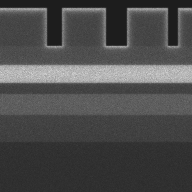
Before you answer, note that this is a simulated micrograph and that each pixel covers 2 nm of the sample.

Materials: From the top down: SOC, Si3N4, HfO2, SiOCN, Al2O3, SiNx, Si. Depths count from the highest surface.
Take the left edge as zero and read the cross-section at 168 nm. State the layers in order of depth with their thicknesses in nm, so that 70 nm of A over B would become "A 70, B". SOC 76, Si3N4 38, HfO2 36, SiOCN 22, Al2O3 42, SiNx 54, Si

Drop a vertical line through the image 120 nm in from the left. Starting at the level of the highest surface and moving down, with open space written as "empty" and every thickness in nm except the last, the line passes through empty 76, Si3N4 38, HfO2 36, SiOCN 22, Al2O3 42, SiNx 54, Si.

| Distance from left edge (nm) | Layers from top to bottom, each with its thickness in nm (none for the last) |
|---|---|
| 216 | empty 76, Si3N4 38, HfO2 36, SiOCN 22, Al2O3 42, SiNx 54, Si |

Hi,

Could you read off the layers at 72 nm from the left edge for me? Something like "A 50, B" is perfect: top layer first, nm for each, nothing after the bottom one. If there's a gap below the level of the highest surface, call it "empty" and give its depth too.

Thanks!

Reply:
SOC 76, Si3N4 38, HfO2 36, SiOCN 22, Al2O3 42, SiNx 54, Si